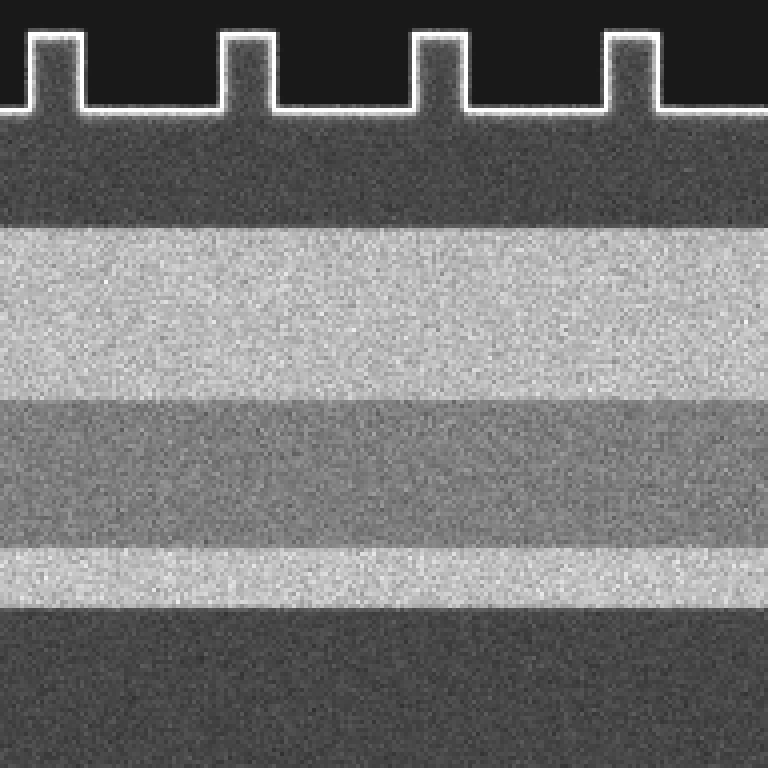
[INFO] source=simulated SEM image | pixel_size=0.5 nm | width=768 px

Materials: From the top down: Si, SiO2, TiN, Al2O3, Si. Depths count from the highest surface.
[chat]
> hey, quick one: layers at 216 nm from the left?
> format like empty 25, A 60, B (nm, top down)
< Si 98, SiO2 86, TiN 74, Al2O3 30, Si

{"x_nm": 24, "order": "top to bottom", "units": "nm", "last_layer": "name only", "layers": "Si 98, SiO2 86, TiN 74, Al2O3 30, Si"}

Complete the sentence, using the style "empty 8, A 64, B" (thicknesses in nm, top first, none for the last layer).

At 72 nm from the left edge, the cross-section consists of empty 38, Si 60, SiO2 86, TiN 74, Al2O3 30, Si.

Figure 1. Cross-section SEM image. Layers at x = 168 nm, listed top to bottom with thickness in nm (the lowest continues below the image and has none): empty 38, Si 60, SiO2 86, TiN 74, Al2O3 30, Si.